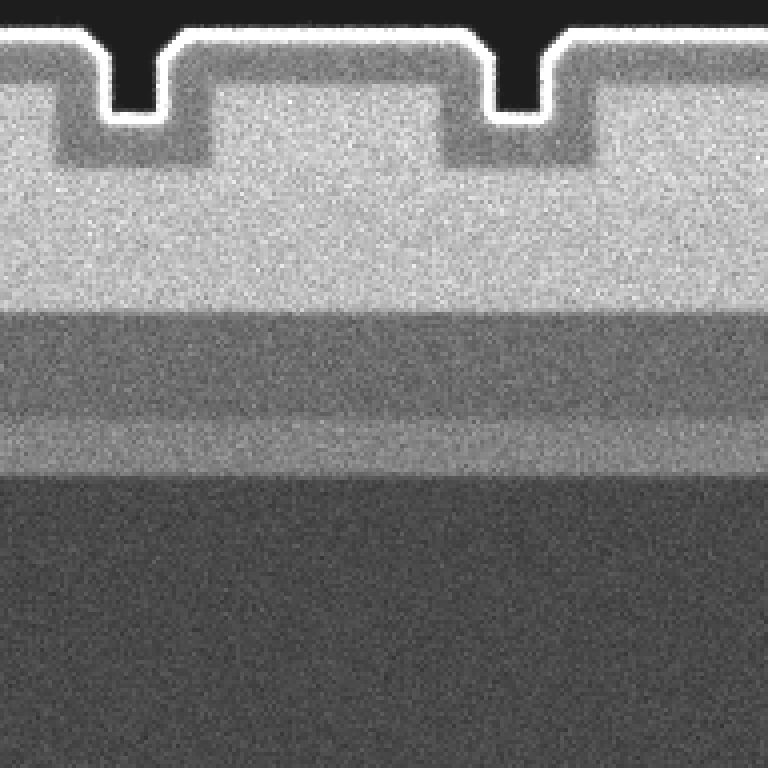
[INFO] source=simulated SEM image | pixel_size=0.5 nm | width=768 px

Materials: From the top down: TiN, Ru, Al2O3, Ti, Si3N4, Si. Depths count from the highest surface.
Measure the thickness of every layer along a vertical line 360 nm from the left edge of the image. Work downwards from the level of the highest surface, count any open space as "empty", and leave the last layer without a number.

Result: TiN 26, Ru 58, Al2O3 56, Ti 54, Si3N4 28, Si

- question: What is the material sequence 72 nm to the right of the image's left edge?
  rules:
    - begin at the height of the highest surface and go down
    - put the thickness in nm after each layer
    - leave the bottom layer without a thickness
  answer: empty 42, TiN 26, Ru 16, Al2O3 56, Ti 54, Si3N4 28, Si